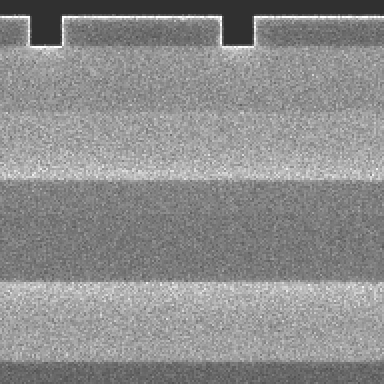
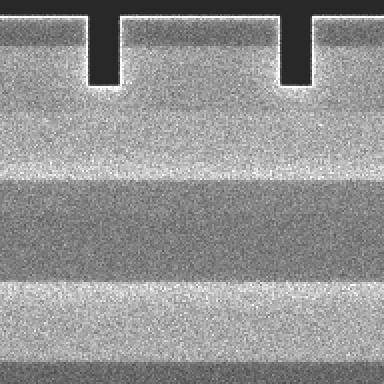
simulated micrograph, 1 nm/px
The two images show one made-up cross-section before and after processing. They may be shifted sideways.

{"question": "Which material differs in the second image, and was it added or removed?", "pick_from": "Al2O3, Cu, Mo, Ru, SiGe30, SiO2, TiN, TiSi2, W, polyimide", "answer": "Ru, removed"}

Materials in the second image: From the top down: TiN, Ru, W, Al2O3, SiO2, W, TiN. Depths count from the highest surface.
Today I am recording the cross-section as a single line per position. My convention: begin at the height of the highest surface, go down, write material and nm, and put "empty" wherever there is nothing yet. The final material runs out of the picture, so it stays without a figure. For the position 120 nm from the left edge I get TiN 30, Ru 66, W 68, Al2O3 34, SiO2 68, W 80, TiN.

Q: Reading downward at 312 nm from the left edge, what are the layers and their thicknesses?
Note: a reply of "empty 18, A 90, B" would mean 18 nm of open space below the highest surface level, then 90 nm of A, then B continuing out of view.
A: TiN 30, Ru 66, W 68, Al2O3 34, SiO2 68, W 80, TiN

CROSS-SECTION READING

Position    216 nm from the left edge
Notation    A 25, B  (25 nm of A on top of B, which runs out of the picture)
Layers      TiN 30, Ru 66, W 68, Al2O3 34, SiO2 68, W 80, TiN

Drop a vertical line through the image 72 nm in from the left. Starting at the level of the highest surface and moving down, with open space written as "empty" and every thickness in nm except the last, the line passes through TiN 30, Ru 66, W 68, Al2O3 34, SiO2 68, W 80, TiN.